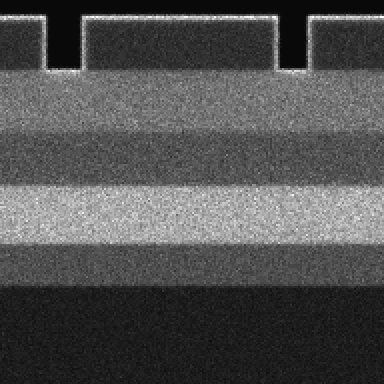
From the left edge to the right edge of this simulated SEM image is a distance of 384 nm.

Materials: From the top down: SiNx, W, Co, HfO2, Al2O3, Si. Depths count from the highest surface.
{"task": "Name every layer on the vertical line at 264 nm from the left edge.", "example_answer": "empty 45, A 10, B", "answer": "SiNx 54, W 62, Co 54, HfO2 58, Al2O3 42, Si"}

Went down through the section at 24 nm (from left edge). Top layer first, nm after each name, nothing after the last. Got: SiNx 54, W 62, Co 54, HfO2 58, Al2O3 42, Si